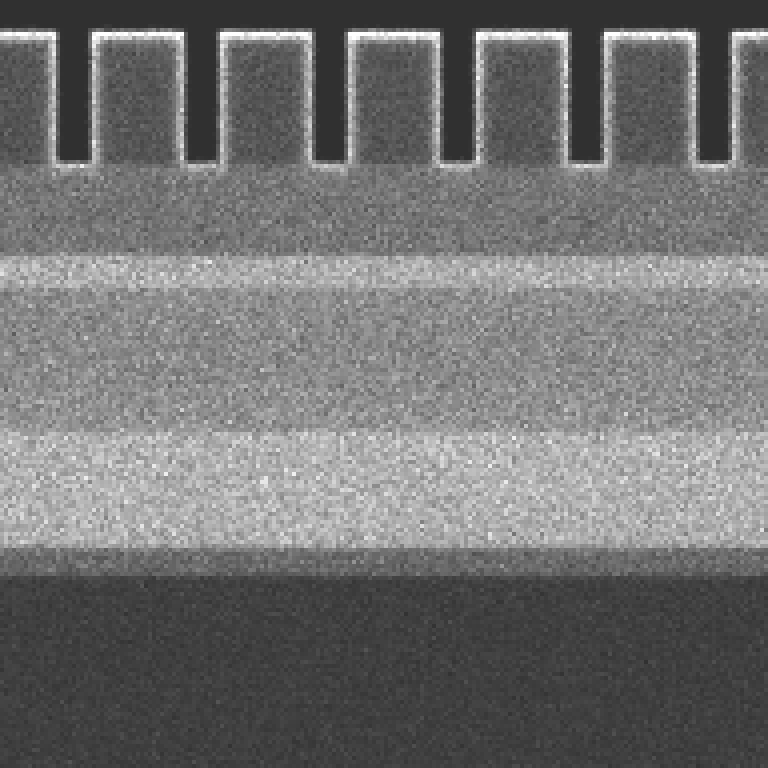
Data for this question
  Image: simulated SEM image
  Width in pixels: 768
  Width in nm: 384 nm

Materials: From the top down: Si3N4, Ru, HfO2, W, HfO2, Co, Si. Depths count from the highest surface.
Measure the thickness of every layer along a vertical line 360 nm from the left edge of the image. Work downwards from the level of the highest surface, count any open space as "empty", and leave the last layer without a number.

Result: empty 66, Ru 46, HfO2 16, W 72, HfO2 58, Co 14, Si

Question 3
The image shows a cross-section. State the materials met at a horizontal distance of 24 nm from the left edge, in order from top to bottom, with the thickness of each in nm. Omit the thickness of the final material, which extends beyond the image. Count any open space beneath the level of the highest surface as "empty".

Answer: Si3N4 66, Ru 46, HfO2 16, W 72, HfO2 58, Co 14, Si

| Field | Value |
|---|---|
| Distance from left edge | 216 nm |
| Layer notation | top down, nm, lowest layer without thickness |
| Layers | Si3N4 66, Ru 46, HfO2 16, W 72, HfO2 58, Co 14, Si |